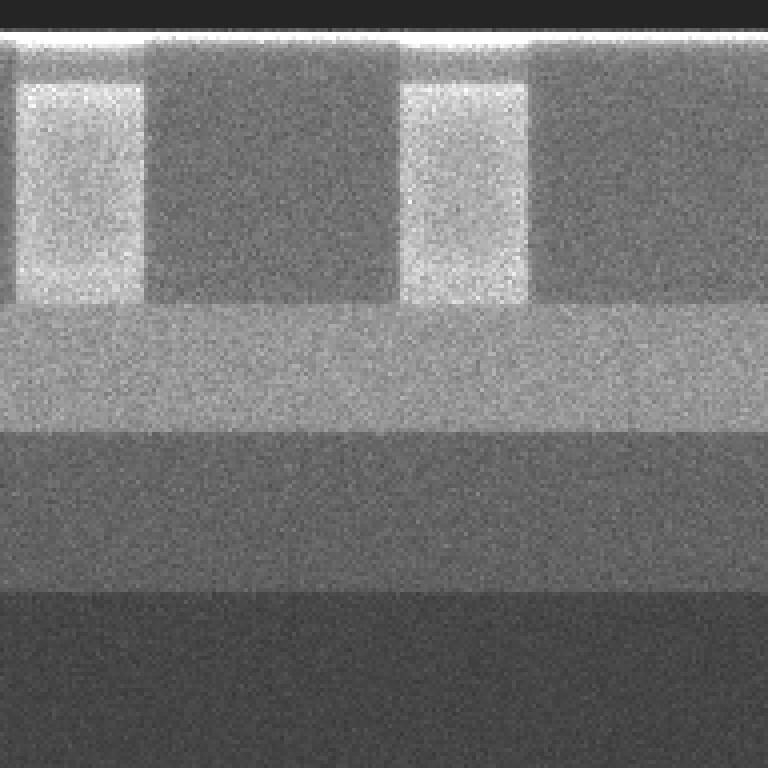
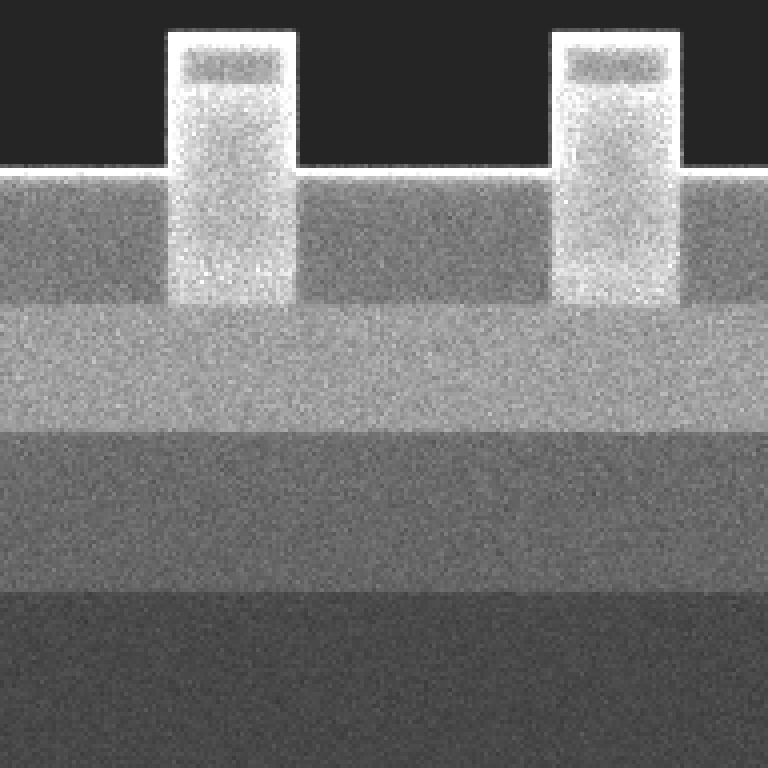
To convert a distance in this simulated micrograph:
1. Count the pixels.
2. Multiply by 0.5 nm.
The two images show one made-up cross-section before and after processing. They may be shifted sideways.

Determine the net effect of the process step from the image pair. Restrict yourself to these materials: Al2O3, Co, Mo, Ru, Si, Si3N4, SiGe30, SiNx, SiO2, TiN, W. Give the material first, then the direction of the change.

Si3N4: removed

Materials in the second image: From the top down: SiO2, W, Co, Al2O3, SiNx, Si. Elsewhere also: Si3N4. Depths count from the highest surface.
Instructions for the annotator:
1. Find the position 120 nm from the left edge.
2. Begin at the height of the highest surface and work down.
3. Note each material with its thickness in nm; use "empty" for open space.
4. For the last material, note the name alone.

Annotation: SiO2 26, W 96, Co 14, Al2O3 64, SiNx 80, Si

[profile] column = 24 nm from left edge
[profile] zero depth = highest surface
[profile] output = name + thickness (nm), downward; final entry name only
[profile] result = empty 68, Si3N4 68, Al2O3 64, SiNx 80, Si